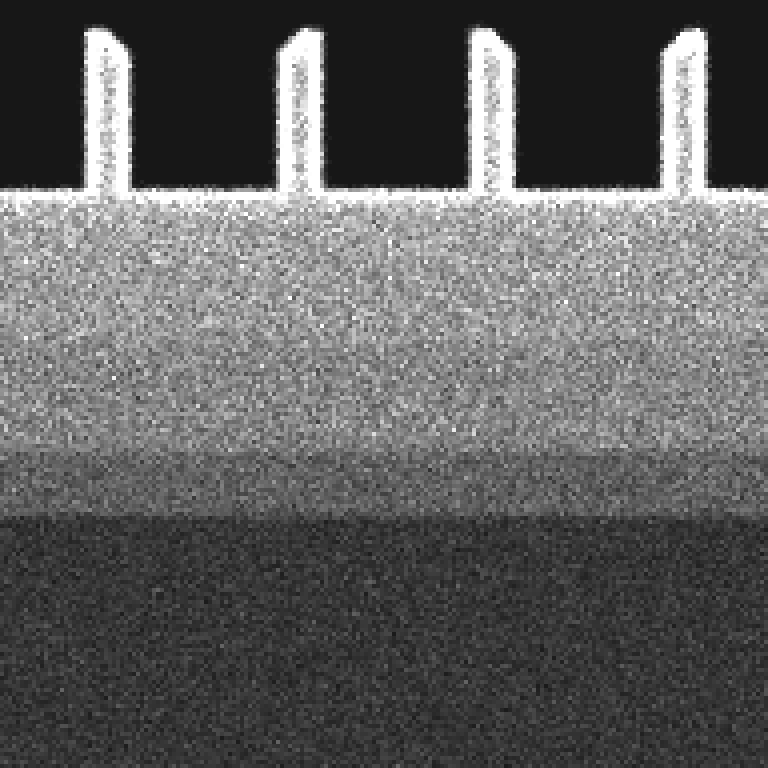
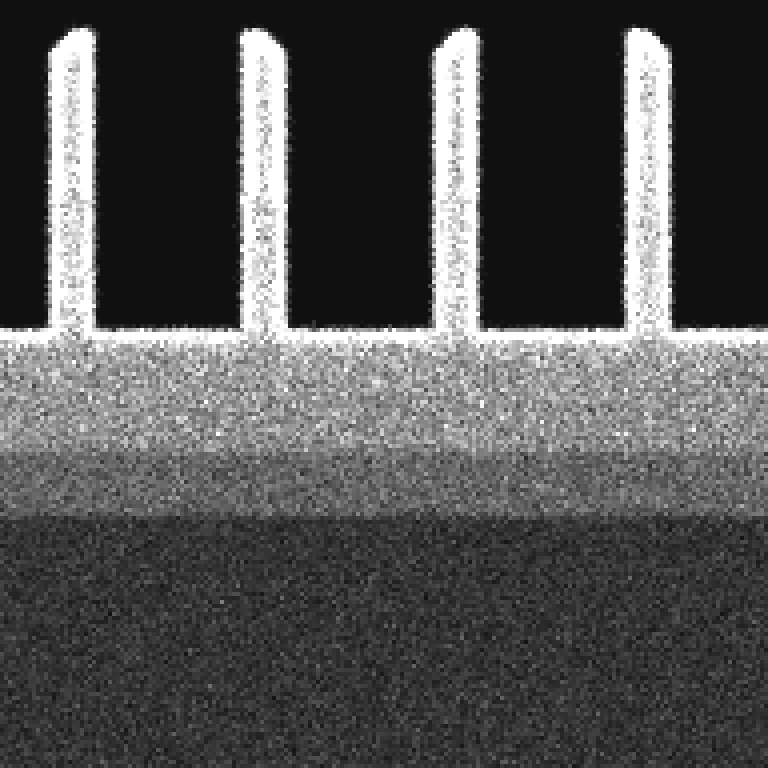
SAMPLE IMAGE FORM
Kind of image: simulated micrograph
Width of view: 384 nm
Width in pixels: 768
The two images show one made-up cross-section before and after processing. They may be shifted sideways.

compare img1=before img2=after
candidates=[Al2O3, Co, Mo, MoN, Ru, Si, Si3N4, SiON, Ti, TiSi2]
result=removed:Ru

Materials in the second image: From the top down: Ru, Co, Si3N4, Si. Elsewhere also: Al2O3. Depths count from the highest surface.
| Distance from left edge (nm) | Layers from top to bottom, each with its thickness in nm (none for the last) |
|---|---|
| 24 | empty 150, Ru 6, Co 54, Si3N4 32, Si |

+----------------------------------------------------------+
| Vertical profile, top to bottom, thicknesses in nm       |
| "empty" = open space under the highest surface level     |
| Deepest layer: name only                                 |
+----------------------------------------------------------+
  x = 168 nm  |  empty 150, Ru 6, Co 54, Si3N4 32, Si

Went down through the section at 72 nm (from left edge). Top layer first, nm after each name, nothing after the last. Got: empty 150, Ru 6, Co 54, Si3N4 32, Si